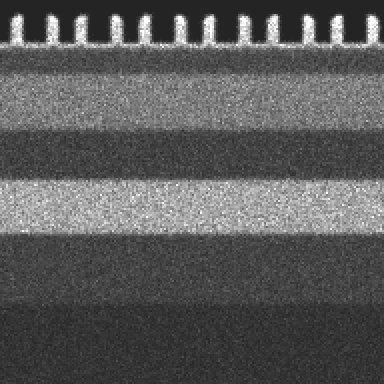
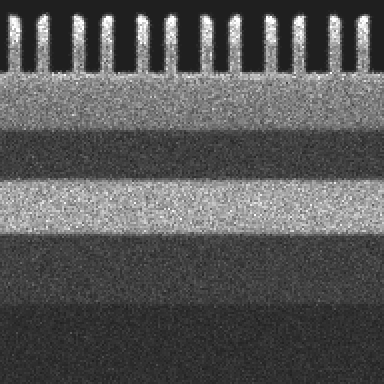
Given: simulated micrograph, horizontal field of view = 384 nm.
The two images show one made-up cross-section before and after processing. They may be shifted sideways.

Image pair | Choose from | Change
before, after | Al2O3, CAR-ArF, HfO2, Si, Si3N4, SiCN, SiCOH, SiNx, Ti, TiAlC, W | Si3N4 (removed)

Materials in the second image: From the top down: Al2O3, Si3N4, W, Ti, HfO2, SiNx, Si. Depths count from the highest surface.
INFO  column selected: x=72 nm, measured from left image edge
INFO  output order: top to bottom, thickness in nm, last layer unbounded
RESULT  empty 58, W 56, Ti 50, HfO2 54, SiNx 70, Si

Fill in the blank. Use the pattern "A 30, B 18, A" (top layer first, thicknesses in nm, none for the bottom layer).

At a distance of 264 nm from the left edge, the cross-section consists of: empty 58, W 56, Ti 50, HfO2 54, SiNx 70, Si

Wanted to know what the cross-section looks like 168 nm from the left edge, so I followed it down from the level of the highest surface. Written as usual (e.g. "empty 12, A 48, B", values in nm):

empty 2, Al2O3 26, Si3N4 30, W 56, Ti 50, HfO2 54, SiNx 70, Si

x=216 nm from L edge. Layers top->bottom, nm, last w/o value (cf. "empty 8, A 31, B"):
empty 58, W 56, Ti 50, HfO2 54, SiNx 70, Si